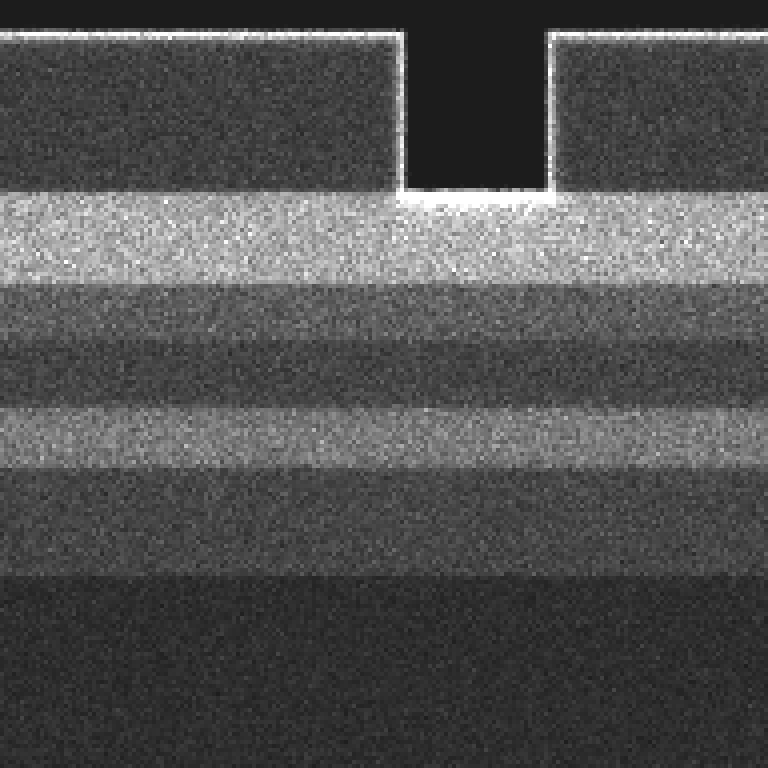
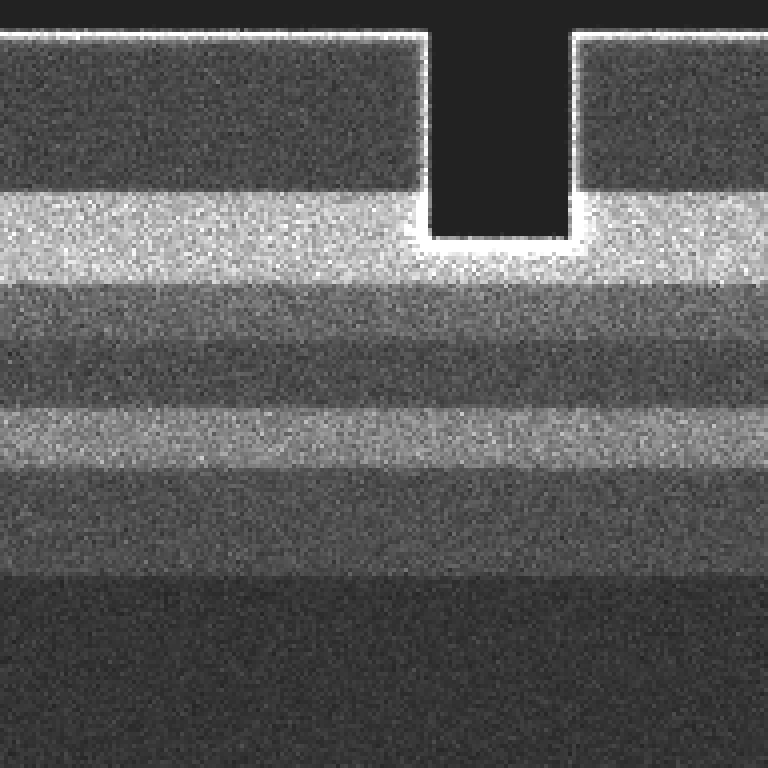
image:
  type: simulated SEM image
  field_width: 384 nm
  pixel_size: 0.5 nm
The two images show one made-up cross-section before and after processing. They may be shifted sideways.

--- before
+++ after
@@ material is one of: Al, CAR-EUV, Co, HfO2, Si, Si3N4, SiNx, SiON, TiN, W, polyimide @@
HfO2 removed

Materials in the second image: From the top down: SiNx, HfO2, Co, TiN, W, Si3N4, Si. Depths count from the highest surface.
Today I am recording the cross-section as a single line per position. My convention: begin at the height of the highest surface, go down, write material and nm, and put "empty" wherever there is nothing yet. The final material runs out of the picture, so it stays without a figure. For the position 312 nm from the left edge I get SiNx 80, HfO2 46, Co 28, TiN 34, W 30, Si3N4 54, Si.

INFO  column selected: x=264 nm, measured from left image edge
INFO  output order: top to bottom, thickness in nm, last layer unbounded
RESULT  empty 104, HfO2 22, Co 28, TiN 34, W 30, Si3N4 54, Si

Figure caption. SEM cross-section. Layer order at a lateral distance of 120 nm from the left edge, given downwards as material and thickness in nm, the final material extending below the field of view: SiNx 80, HfO2 46, Co 28, TiN 34, W 30, Si3N4 54, Si